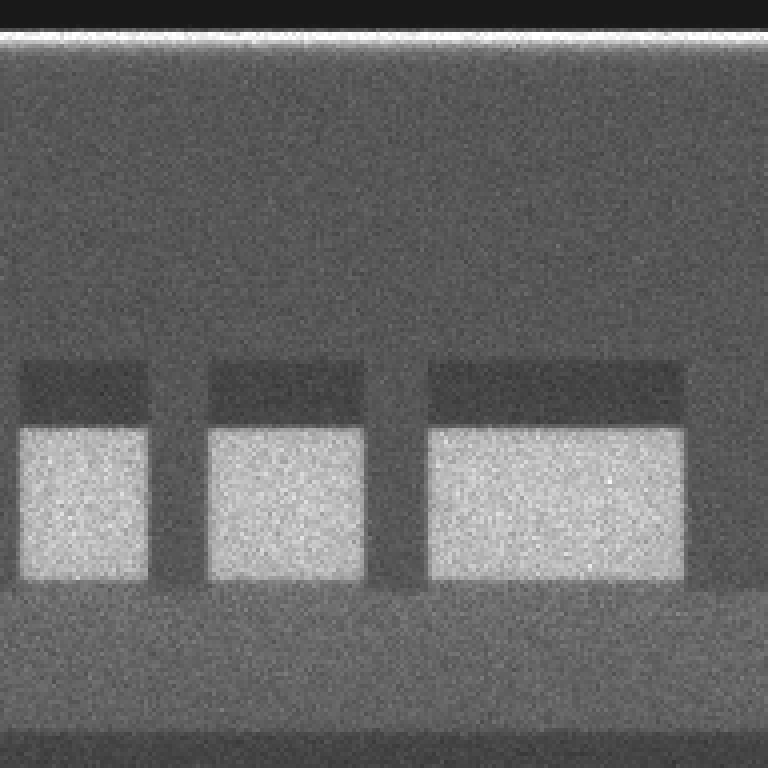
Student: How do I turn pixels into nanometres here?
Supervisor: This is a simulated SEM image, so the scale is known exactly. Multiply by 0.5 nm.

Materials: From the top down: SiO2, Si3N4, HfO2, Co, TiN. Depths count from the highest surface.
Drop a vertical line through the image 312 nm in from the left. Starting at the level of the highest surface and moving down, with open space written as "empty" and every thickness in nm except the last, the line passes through SiO2 164, Si3N4 34, HfO2 76, Co 76, TiN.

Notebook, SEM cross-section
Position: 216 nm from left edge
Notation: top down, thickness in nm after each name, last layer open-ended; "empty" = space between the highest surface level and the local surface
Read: SiO2 164, Si3N4 34, HfO2 76, Co 76, TiN